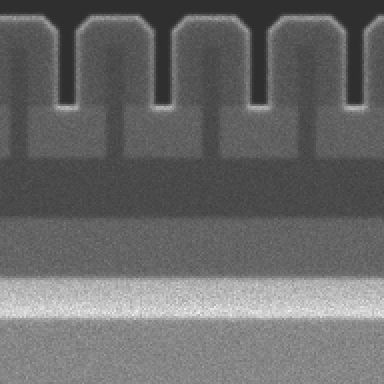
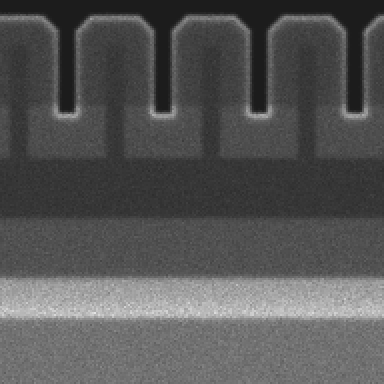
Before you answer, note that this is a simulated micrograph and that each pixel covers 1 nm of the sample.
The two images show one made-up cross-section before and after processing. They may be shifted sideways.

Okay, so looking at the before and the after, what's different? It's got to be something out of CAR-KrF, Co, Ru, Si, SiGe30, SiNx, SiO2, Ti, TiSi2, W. SiNx, removed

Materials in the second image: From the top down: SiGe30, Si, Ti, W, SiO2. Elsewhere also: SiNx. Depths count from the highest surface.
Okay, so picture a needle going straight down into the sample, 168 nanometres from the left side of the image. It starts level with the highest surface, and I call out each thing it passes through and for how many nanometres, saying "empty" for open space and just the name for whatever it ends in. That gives empty 98, SiNx 44, Si 60, Ti 60, W 40, SiO2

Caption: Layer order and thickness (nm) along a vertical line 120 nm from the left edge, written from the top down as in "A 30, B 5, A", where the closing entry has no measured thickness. SiGe30 30, Si 172, Ti 60, W 40, SiO2